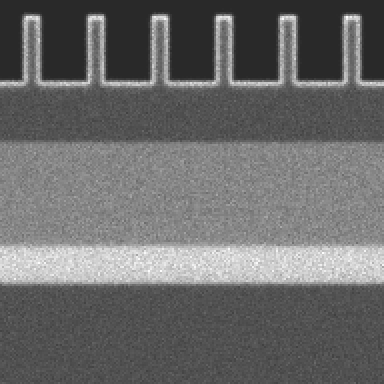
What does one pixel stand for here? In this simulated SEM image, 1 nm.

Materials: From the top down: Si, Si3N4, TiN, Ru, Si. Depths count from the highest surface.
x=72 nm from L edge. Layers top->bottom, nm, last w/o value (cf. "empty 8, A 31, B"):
empty 66, Si 60, Si3N4 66, TiN 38, Ru 38, Si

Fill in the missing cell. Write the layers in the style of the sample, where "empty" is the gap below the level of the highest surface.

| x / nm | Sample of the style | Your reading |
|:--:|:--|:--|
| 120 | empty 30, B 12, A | empty 66, Si 60, Si3N4 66, TiN 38, Ru 38, Si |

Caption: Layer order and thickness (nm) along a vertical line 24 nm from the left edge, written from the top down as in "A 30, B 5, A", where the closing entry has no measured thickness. Si 126, Si3N4 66, TiN 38, Ru 38, Si